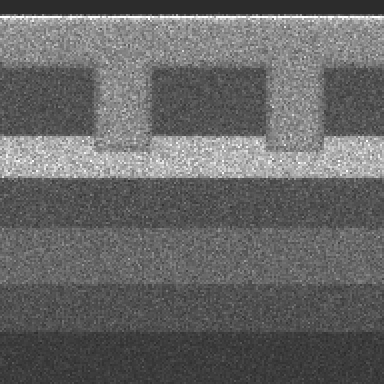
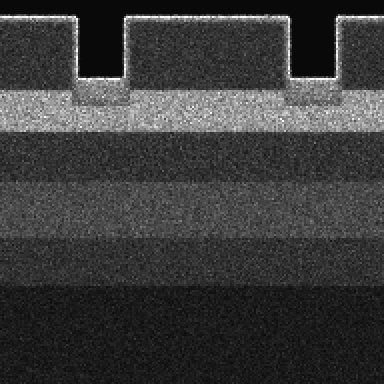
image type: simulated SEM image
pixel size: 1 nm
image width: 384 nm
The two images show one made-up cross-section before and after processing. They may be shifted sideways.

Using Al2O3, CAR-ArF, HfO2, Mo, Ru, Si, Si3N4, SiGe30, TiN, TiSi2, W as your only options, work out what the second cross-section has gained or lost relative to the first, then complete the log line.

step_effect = removed W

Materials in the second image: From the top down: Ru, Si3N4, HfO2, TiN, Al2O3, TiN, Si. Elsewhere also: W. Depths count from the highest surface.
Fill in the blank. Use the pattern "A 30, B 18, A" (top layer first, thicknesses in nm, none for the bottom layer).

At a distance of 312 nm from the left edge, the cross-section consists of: empty 62, W 22, Ru 6, HfO2 26, TiN 50, Al2O3 56, TiN 48, Si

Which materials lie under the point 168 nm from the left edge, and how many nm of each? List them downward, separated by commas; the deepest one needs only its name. Ru 6, Si3N4 68, HfO2 42, TiN 50, Al2O3 56, TiN 48, Si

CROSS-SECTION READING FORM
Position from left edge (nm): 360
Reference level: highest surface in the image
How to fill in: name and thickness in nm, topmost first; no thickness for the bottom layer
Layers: Ru 6, Si3N4 68, HfO2 42, TiN 50, Al2O3 56, TiN 48, Si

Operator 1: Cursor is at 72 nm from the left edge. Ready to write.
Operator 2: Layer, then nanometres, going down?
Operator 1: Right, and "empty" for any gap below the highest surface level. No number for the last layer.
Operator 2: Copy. Ru 90, HfO2 26, TiN 50, Al2O3 56, TiN 48, Si